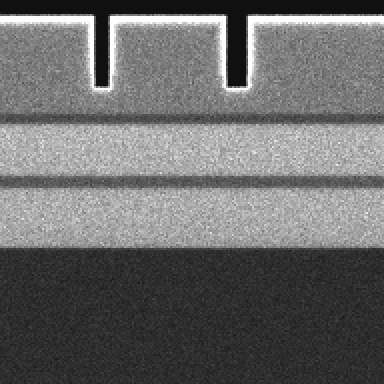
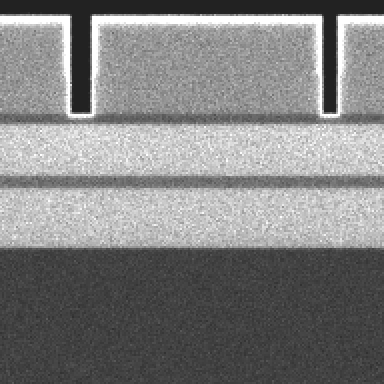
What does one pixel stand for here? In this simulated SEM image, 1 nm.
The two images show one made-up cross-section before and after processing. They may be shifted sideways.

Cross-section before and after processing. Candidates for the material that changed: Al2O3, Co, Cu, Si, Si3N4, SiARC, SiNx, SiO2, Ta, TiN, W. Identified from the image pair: Co (removed).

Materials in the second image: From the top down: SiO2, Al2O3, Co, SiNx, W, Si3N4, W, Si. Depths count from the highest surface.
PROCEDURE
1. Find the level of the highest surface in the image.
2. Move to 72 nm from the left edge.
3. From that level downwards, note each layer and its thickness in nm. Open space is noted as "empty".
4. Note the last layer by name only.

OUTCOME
empty 98, SiNx 10, W 52, Si3N4 12, W 60, Si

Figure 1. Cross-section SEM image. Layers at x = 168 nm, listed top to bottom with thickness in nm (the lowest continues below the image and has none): SiO2 16, Al2O3 42, Co 40, SiNx 10, W 52, Si3N4 12, W 60, Si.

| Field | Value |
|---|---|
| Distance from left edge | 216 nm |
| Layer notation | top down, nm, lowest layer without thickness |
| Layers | SiO2 16, Al2O3 42, Co 40, SiNx 10, W 52, Si3N4 12, W 60, Si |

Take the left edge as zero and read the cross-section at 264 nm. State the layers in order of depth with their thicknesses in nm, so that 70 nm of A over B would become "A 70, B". SiO2 16, Al2O3 42, Co 40, SiNx 10, W 52, Si3N4 12, W 60, Si